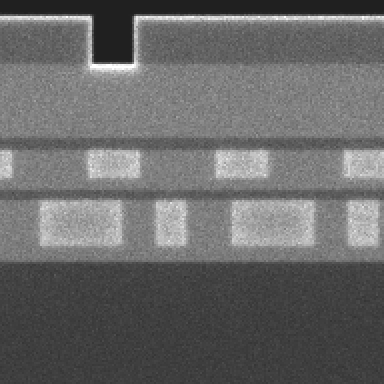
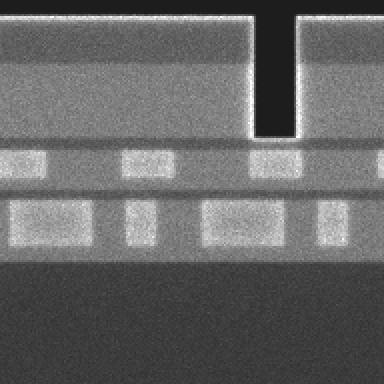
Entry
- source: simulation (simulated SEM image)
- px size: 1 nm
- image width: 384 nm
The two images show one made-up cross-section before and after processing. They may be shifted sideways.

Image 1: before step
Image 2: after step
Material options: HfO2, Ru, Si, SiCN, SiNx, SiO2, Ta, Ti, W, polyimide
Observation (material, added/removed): SiO2, removed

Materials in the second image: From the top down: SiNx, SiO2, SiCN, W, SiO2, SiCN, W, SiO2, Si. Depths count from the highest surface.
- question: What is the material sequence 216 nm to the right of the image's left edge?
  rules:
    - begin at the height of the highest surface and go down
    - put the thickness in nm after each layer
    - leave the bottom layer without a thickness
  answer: SiNx 48, SiO2 74, SiCN 12, SiO2 40, SiCN 10, W 46, SiO2 16, Si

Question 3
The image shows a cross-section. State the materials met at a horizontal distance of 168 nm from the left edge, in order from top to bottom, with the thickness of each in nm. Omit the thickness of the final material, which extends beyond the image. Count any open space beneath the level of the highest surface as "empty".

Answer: SiNx 48, SiO2 74, SiCN 12, W 28, SiO2 12, SiCN 10, SiO2 62, Si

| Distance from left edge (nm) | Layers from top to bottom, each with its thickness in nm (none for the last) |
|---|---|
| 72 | SiNx 48, SiO2 74, SiCN 12, SiO2 40, SiCN 10, W 46, SiO2 16, Si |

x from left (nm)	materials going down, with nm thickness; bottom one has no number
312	SiNx 48, SiO2 74, SiCN 12, SiO2 40, SiCN 10, SiO2 62, Si